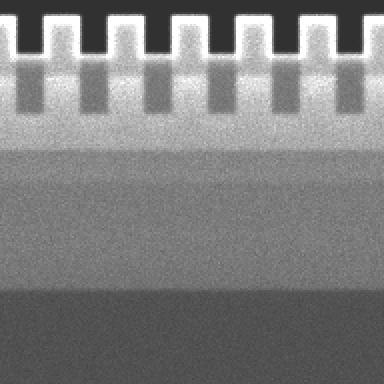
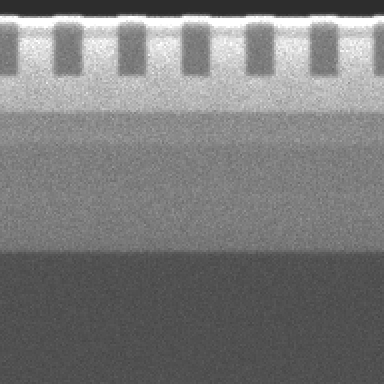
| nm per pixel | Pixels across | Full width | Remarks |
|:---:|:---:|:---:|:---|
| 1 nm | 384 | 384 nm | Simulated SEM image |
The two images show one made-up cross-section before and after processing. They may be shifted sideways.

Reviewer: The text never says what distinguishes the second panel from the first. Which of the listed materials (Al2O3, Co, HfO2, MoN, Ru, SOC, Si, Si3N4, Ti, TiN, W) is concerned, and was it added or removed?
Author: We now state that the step removed Al2O3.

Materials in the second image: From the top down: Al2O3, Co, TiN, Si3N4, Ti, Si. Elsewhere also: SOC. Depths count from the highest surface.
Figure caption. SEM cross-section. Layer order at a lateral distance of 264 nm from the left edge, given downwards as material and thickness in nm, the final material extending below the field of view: SOC 60, Co 36, TiN 32, Si3N4 56, Ti 52, Si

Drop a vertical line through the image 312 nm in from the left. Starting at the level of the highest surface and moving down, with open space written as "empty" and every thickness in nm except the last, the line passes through SOC 60, Co 36, TiN 32, Si3N4 56, Ti 52, Si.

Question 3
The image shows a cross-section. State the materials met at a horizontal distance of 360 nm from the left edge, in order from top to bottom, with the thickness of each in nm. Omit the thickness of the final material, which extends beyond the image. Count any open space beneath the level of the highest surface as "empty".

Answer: empty 2, Al2O3 20, Co 74, TiN 32, Si3N4 56, Ti 52, Si